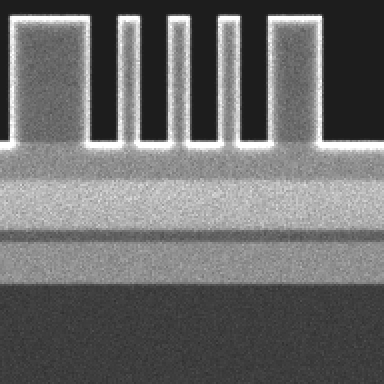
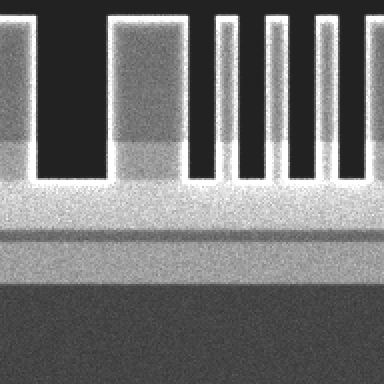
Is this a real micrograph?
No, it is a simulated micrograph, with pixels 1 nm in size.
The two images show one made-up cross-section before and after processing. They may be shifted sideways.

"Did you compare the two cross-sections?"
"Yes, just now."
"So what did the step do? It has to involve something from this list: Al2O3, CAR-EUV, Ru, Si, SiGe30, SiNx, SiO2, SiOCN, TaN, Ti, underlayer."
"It removed SiO2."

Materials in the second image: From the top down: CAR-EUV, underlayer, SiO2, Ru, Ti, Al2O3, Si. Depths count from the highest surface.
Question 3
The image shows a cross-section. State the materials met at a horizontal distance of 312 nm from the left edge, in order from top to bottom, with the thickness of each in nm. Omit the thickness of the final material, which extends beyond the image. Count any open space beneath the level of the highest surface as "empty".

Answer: empty 164, Ru 50, Ti 12, Al2O3 42, Si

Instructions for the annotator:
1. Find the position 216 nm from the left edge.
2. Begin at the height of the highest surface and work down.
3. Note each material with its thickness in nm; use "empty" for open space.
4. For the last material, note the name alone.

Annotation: CAR-EUV 72, underlayer 54, SiO2 38, Ru 50, Ti 12, Al2O3 42, Si